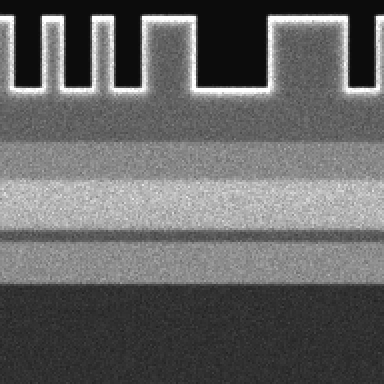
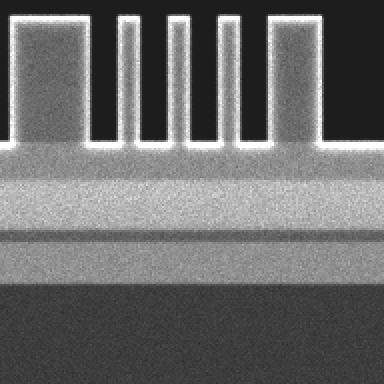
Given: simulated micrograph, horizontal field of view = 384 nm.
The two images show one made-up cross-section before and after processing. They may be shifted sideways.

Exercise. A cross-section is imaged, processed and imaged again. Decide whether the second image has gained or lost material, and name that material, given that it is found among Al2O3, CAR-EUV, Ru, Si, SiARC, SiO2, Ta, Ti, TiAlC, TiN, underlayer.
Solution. removed: underlayer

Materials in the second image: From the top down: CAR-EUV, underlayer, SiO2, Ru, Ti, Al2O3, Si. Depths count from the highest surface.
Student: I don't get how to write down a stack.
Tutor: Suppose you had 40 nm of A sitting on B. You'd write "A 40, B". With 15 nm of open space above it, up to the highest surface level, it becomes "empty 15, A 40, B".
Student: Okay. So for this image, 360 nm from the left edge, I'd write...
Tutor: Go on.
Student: empty 126, SiO2 38, Ru 50, Ti 12, Al2O3 42, Si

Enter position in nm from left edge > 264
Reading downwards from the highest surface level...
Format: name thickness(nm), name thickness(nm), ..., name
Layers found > empty 126, SiO2 38, Ru 50, Ti 12, Al2O3 42, Si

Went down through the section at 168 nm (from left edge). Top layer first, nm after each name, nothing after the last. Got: CAR-EUV 72, underlayer 54, SiO2 38, Ru 50, Ti 12, Al2O3 42, Si